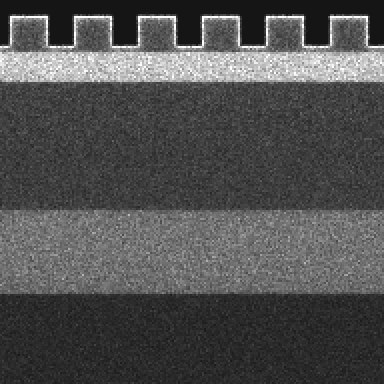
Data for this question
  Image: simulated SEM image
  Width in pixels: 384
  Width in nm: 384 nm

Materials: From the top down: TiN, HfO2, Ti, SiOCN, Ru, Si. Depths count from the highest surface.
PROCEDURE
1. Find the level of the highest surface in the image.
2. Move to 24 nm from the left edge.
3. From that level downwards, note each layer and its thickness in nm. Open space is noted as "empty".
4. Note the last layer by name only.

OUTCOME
TiN 36, HfO2 30, Ti 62, SiOCN 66, Ru 84, Si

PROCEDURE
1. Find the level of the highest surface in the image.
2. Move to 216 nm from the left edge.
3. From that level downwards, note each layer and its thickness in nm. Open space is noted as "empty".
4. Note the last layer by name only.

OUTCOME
TiN 36, HfO2 30, Ti 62, SiOCN 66, Ru 84, Si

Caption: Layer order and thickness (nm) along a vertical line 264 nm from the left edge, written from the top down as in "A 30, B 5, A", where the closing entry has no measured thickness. empty 30, TiN 6, HfO2 30, Ti 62, SiOCN 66, Ru 84, Si